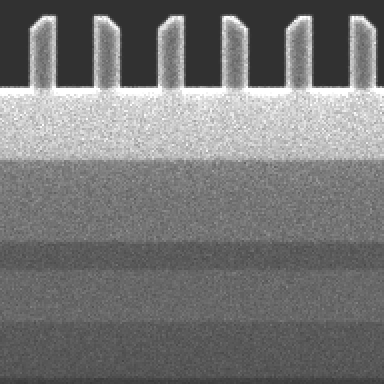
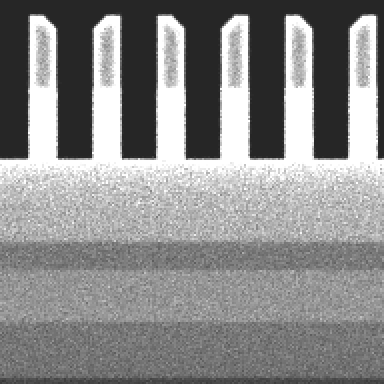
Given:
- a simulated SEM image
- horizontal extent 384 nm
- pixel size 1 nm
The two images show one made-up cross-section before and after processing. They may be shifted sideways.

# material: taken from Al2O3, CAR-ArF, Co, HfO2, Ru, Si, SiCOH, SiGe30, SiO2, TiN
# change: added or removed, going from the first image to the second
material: HfO2
change: removed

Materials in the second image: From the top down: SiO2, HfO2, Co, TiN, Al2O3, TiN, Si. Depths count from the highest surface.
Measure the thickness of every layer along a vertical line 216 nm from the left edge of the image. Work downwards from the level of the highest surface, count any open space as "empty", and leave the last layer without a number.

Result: empty 144, Co 82, TiN 28, Al2O3 52, TiN 56, Si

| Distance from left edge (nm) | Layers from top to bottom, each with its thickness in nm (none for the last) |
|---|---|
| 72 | empty 144, Co 82, TiN 28, Al2O3 52, TiN 56, Si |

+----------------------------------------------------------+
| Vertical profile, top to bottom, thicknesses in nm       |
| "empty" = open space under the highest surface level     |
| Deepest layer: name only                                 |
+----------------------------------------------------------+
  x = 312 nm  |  empty 144, Co 82, TiN 28, Al2O3 52, TiN 56, Si